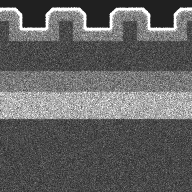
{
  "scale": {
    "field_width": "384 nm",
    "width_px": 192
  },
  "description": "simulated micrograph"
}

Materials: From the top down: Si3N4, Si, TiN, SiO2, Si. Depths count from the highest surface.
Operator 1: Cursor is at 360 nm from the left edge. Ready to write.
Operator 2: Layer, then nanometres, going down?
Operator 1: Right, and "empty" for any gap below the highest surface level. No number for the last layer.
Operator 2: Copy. Si3N4 66, Si 60, TiN 42, SiO2 54, Si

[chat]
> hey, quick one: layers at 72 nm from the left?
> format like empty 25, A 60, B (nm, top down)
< empty 40, Si3N4 26, Si 60, TiN 42, SiO2 54, Si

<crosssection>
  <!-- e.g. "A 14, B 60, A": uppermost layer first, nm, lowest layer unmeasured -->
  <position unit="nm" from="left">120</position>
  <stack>Si3N4 26, Si 100, TiN 42, SiO2 54, Si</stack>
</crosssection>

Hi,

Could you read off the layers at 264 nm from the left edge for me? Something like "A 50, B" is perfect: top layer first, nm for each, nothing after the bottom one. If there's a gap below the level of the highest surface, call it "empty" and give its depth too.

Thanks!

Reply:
Si3N4 26, Si 100, TiN 42, SiO2 54, Si